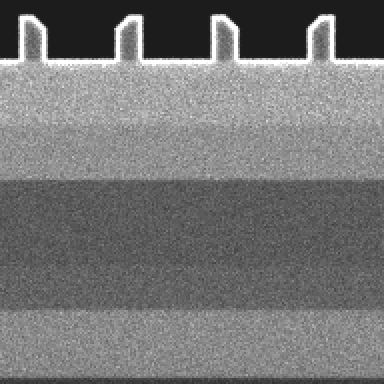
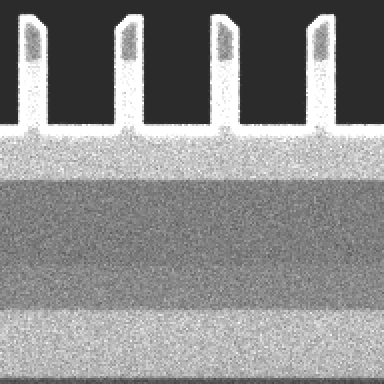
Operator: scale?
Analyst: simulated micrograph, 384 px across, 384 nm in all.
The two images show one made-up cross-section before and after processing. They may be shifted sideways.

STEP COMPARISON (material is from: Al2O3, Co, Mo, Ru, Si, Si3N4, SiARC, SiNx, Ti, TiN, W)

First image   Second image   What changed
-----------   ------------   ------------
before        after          Ru, removed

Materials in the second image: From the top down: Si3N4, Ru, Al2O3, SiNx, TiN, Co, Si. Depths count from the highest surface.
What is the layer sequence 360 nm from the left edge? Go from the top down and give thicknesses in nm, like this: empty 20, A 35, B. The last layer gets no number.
empty 110, Al2O3 54, SiNx 86, TiN 44, Co 68, Si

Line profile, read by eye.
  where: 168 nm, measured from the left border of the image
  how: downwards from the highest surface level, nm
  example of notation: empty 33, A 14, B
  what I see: empty 110, Al2O3 54, SiNx 86, TiN 44, Co 68, Si